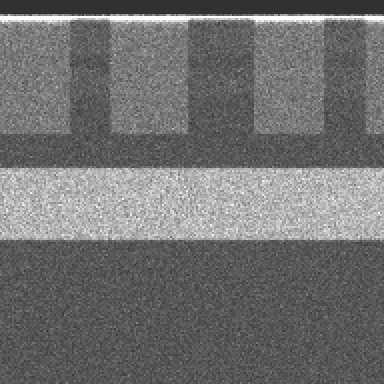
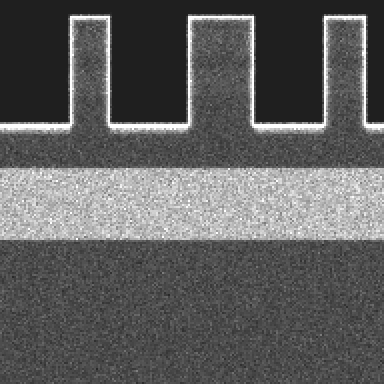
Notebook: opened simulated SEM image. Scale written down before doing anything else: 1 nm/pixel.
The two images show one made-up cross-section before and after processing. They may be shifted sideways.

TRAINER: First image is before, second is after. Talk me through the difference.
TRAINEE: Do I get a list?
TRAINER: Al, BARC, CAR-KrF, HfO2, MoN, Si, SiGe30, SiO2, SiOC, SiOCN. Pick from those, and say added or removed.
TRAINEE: removed: SiOCN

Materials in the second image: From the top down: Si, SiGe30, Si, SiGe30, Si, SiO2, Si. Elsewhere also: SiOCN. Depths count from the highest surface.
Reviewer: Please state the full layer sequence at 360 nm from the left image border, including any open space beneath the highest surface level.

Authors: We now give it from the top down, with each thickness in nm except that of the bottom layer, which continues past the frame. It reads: Si 12, SiGe30 28, Si 12, SiGe30 28, Si 72, SiO2 72, Si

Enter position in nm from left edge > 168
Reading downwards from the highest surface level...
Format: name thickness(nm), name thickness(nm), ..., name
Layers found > empty 108, SiOCN 10, Si 34, SiO2 72, Si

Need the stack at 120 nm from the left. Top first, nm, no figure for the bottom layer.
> empty 108, SiOCN 10, Si 34, SiO2 72, Si